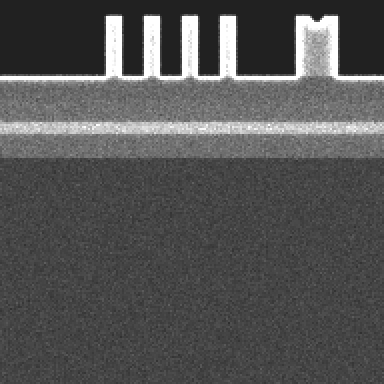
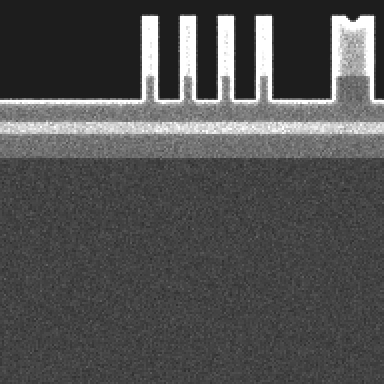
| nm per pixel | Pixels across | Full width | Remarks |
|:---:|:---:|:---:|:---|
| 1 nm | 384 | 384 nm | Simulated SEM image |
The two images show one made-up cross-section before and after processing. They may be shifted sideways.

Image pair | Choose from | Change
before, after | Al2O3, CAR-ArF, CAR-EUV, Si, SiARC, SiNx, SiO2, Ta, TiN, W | SiNx (removed)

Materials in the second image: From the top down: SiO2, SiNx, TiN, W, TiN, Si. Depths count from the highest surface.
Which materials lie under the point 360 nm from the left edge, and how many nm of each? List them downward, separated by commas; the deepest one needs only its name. SiO2 60, SiNx 24, TiN 22, W 12, TiN 24, Si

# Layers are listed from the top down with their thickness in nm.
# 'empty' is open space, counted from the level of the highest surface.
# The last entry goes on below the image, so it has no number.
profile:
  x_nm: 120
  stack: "empty 84, TiN 22, W 12, TiN 24, Si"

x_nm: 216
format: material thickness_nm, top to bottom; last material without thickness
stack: empty 84, TiN 22, W 12, TiN 24, Si